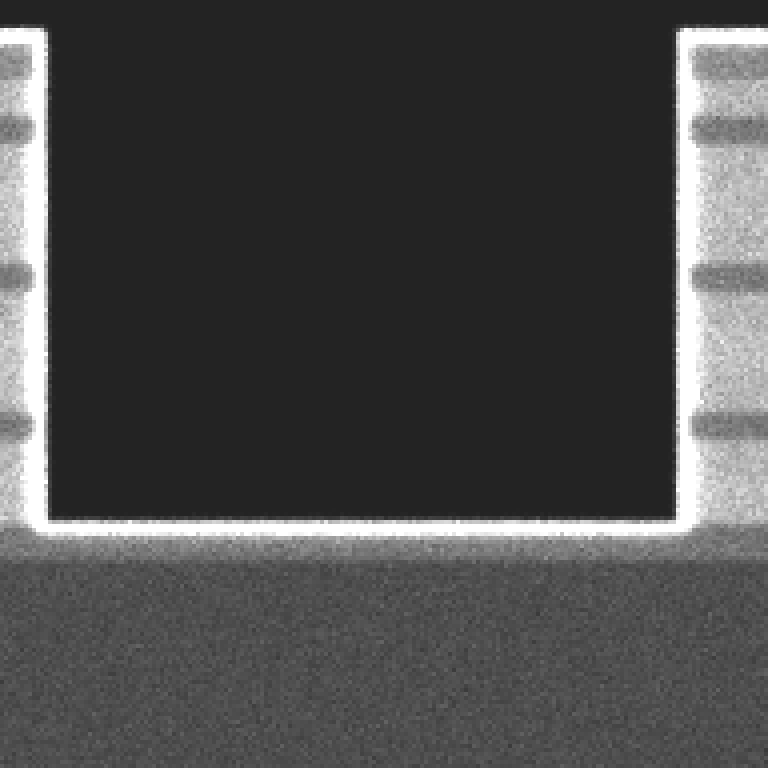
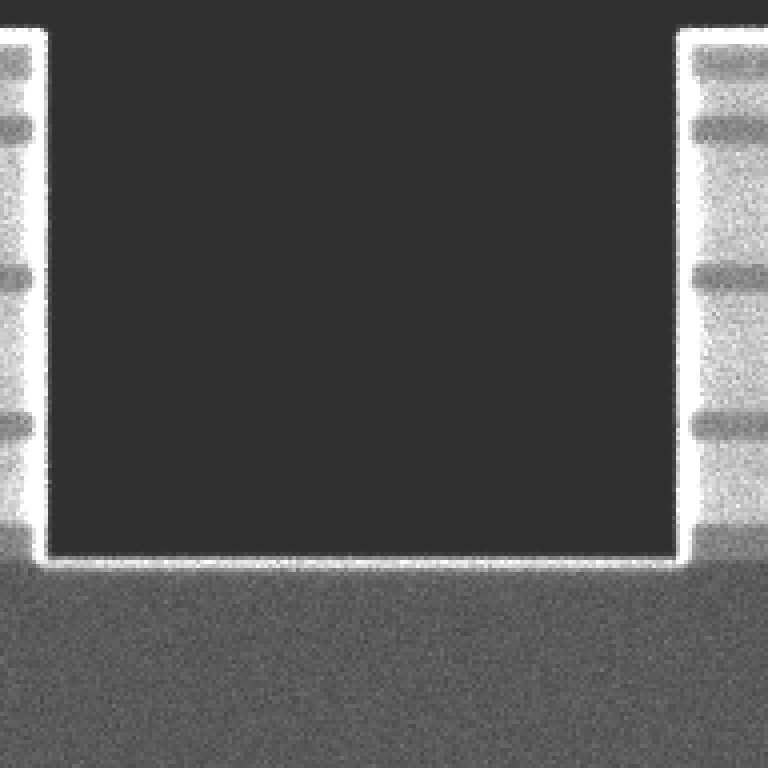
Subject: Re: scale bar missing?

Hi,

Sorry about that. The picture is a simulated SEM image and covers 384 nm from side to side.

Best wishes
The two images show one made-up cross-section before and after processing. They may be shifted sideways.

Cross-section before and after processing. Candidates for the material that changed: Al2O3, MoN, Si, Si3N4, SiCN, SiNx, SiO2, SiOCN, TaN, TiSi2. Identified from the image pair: SiOCN (removed).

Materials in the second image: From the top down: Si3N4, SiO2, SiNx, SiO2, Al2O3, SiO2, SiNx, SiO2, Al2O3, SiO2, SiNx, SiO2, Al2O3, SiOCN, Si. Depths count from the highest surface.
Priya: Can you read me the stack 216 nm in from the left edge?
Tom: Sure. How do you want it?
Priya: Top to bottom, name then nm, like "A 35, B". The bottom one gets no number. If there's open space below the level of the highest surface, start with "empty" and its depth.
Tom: empty 264, Si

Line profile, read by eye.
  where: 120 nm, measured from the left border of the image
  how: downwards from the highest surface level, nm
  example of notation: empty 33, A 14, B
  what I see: empty 264, Si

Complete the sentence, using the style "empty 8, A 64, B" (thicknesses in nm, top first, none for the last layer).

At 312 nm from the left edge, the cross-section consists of empty 264, Si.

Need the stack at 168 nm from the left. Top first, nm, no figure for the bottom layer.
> empty 264, Si